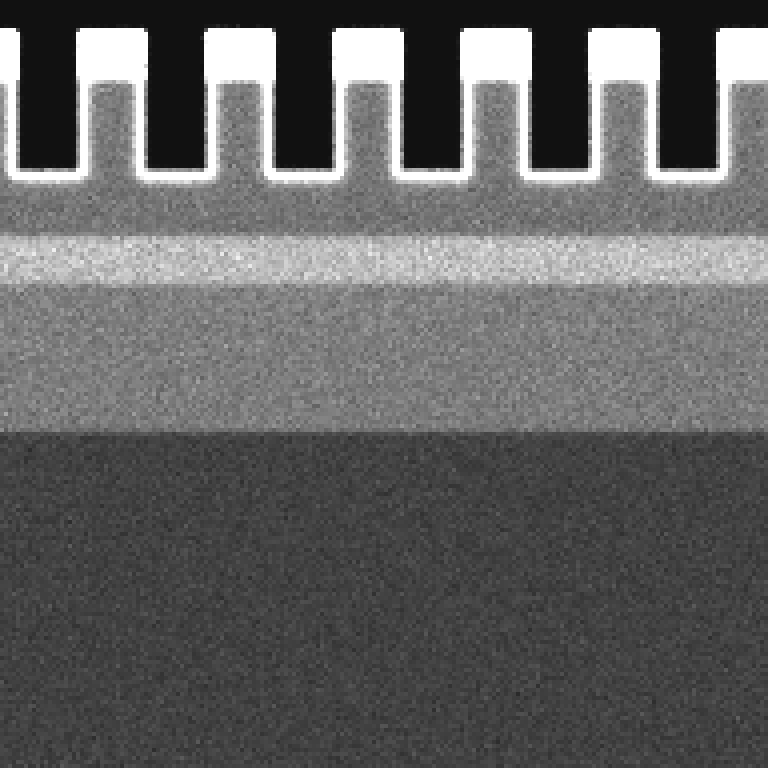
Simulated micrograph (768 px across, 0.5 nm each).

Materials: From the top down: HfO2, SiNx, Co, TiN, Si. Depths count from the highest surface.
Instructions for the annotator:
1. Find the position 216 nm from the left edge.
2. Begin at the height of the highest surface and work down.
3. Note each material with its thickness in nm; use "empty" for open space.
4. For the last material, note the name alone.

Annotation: empty 70, SiNx 32, Co 24, TiN 74, Si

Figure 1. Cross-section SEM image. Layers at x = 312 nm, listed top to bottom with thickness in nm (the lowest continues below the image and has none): HfO2 24, SiNx 78, Co 24, TiN 74, Si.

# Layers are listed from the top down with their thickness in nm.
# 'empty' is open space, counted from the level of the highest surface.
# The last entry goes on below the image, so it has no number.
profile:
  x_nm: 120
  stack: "HfO2 24, SiNx 78, Co 24, TiN 74, Si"